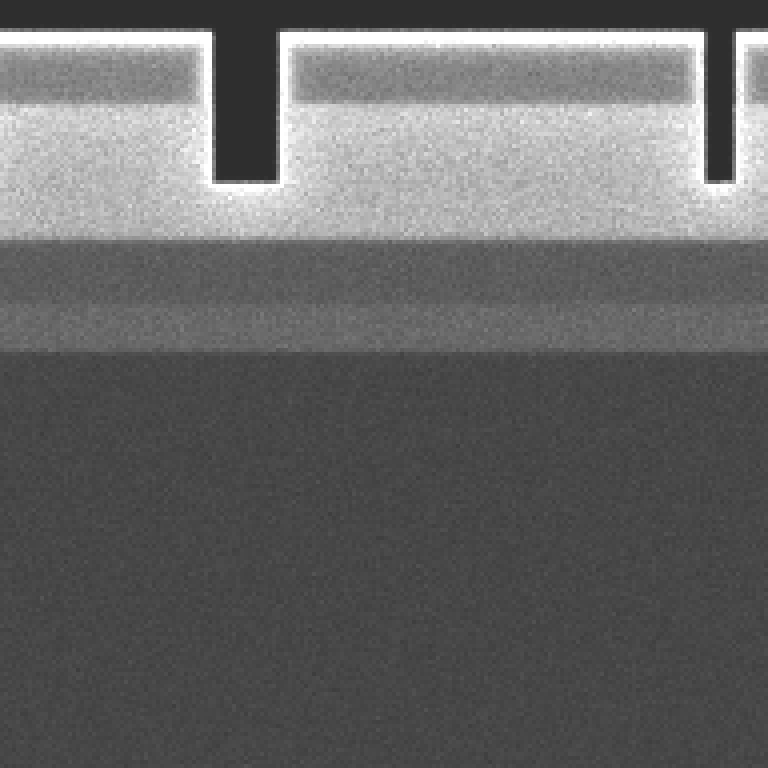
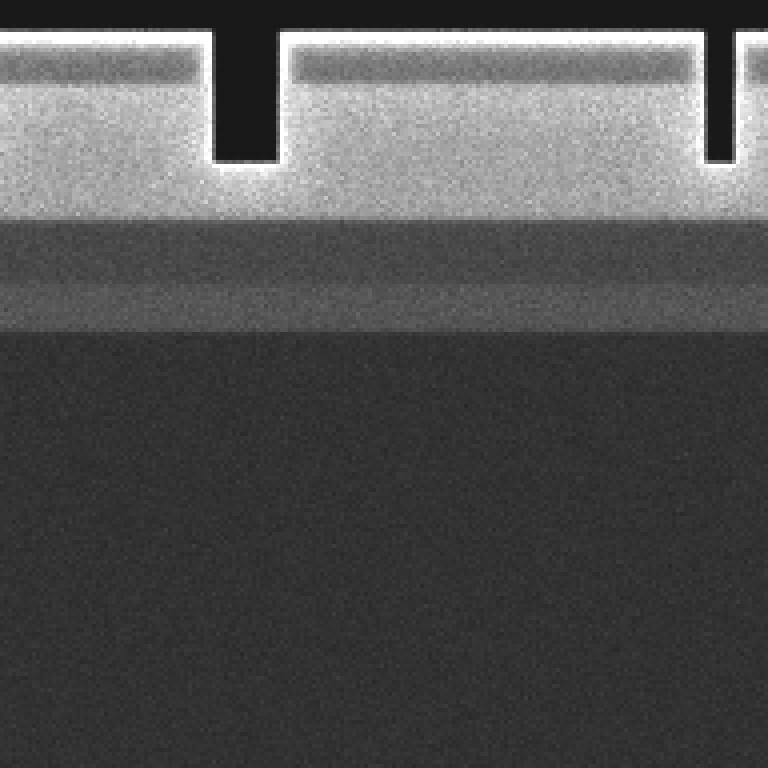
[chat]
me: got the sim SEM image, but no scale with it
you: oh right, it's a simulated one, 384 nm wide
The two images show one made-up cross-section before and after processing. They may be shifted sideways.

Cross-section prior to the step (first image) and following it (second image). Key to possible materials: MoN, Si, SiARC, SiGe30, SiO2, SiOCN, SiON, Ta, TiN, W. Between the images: SiO2 was removed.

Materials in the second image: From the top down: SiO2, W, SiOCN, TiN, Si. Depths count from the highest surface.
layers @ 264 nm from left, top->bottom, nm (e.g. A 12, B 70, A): SiO2 26, W 68, SiOCN 32, TiN 24, Si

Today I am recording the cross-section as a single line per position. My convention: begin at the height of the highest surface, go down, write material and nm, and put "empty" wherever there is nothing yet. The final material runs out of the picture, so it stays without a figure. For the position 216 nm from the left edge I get SiO2 26, W 68, SiOCN 32, TiN 24, Si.